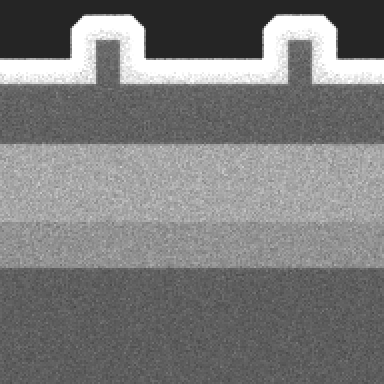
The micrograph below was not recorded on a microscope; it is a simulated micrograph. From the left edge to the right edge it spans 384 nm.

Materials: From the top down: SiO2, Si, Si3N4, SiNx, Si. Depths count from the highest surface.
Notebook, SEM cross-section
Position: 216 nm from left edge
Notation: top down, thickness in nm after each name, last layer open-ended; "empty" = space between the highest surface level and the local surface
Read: empty 44, SiO2 24, Si 60, Si3N4 78, SiNx 46, Si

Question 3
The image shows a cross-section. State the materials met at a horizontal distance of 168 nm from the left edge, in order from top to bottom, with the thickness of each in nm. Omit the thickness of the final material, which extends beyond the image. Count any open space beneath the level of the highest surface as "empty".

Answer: empty 44, SiO2 24, Si 60, Si3N4 78, SiNx 46, Si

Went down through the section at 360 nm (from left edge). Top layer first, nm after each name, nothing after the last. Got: empty 44, SiO2 24, Si 60, Si3N4 78, SiNx 46, Si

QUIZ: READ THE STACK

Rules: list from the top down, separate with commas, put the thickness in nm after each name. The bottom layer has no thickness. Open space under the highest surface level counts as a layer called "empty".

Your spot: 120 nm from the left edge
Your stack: SiO2 68, Si 60, Si3N4 78, SiNx 46, Si